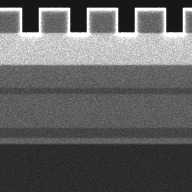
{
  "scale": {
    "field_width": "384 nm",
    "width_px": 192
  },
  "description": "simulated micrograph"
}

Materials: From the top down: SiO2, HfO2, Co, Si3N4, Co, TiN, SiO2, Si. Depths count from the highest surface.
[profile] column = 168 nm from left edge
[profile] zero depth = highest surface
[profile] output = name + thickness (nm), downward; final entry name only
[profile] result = empty 50, HfO2 64, Co 46, Si3N4 12, Co 68, TiN 20, SiO2 12, Si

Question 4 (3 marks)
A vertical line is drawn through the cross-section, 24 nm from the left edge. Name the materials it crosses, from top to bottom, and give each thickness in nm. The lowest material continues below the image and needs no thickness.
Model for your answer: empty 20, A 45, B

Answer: SiO2 50, HfO2 64, Co 46, Si3N4 12, Co 68, TiN 20, SiO2 12, Si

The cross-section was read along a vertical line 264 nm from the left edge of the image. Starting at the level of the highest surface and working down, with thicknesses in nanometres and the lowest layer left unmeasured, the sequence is empty 50, HfO2 64, Co 46, Si3N4 12, Co 68, TiN 20, SiO2 12, Si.